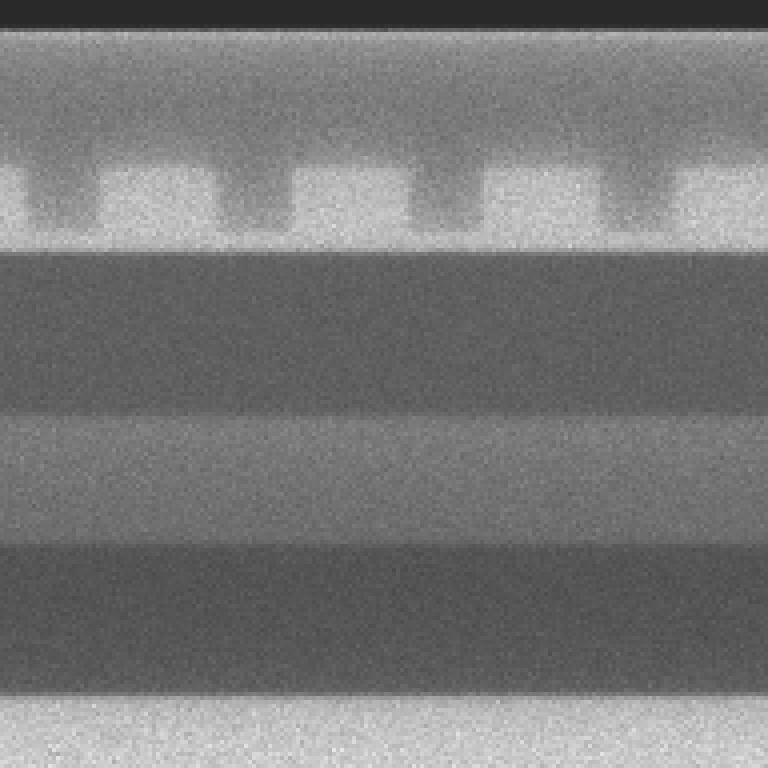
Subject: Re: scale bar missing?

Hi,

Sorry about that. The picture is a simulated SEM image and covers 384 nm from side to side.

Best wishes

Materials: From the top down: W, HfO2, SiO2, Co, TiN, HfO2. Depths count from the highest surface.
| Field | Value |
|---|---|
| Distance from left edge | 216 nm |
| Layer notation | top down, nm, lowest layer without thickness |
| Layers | W 100, HfO2 10, SiO2 82, Co 64, TiN 76, HfO2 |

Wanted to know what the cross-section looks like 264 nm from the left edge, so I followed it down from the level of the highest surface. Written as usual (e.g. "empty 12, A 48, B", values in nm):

W 68, HfO2 42, SiO2 82, Co 64, TiN 76, HfO2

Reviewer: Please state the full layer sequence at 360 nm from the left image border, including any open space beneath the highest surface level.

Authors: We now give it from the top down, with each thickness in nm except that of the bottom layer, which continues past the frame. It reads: W 68, HfO2 42, SiO2 82, Co 64, TiN 76, HfO2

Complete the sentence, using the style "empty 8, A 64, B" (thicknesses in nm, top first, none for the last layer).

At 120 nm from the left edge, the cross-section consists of W 100, HfO2 10, SiO2 82, Co 64, TiN 76, HfO2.